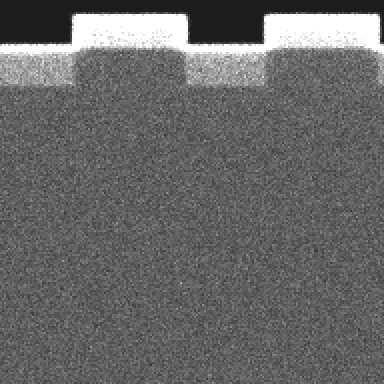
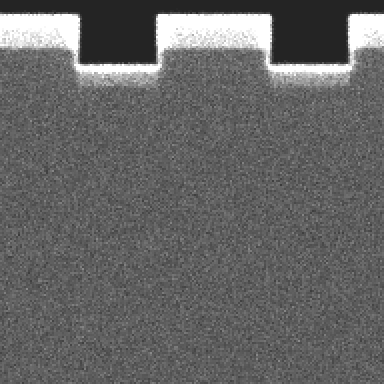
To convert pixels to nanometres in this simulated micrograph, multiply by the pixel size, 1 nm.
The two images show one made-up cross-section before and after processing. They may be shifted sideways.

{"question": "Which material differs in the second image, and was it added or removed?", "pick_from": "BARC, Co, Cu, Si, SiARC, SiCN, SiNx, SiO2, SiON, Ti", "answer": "SiNx, removed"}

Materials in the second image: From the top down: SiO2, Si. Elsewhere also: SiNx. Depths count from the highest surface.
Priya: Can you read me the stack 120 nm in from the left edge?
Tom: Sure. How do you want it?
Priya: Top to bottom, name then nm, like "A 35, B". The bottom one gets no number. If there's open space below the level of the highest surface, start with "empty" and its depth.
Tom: empty 50, SiNx 20, Si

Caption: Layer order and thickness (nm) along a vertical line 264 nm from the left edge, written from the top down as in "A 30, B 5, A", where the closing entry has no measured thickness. SiO2 32, Si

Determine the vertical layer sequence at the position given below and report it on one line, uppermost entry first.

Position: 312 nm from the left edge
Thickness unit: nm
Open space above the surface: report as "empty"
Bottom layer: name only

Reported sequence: empty 50, SiNx 20, Si